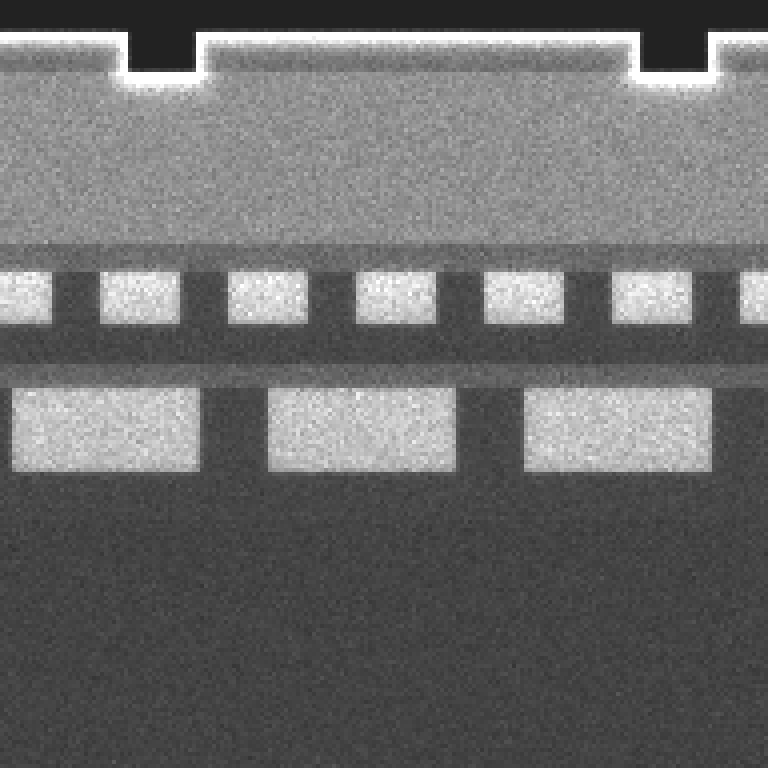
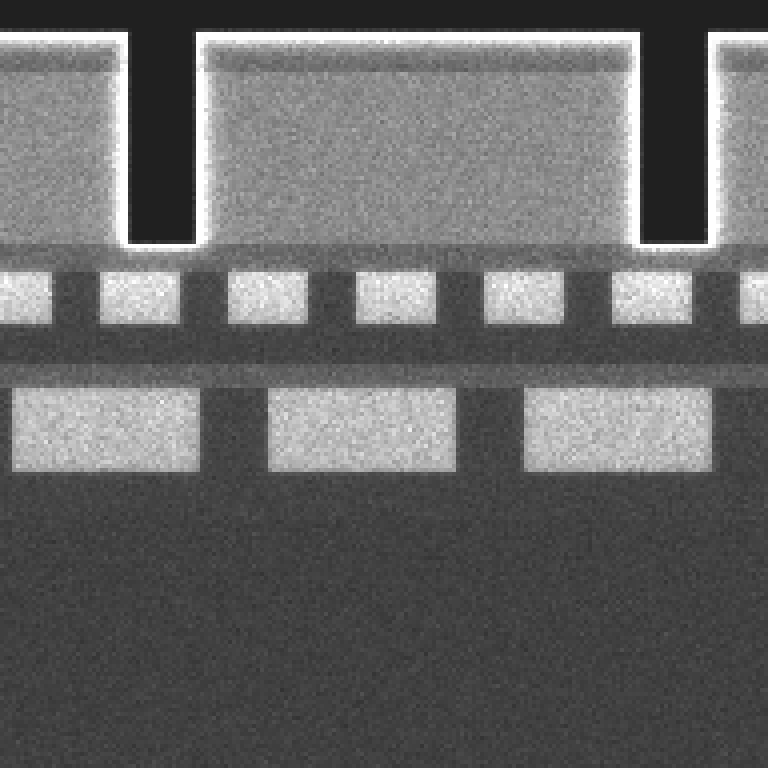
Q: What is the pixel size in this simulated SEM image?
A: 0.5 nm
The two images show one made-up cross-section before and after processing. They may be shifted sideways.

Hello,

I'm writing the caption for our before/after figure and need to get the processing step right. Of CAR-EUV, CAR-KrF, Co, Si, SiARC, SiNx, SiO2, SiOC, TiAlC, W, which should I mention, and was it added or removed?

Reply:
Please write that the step removed SiO2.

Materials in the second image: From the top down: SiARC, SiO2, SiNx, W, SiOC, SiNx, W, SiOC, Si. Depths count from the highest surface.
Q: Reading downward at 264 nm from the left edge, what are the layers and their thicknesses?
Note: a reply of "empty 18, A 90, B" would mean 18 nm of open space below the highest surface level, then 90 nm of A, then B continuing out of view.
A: SiARC 20, SiO2 86, SiNx 14, W 26, SiOC 20, SiNx 12, W 42, SiOC 24, Si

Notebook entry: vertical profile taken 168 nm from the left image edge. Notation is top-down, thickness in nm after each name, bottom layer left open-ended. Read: SiARC 20, SiO2 86, SiNx 14, SiOC 46, SiNx 12, W 42, SiOC 24, Si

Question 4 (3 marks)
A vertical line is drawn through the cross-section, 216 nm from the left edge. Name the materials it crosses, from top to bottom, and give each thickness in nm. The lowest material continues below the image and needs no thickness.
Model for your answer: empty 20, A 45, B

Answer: SiARC 20, SiO2 86, SiNx 14, W 26, SiOC 20, SiNx 12, W 42, SiOC 24, Si